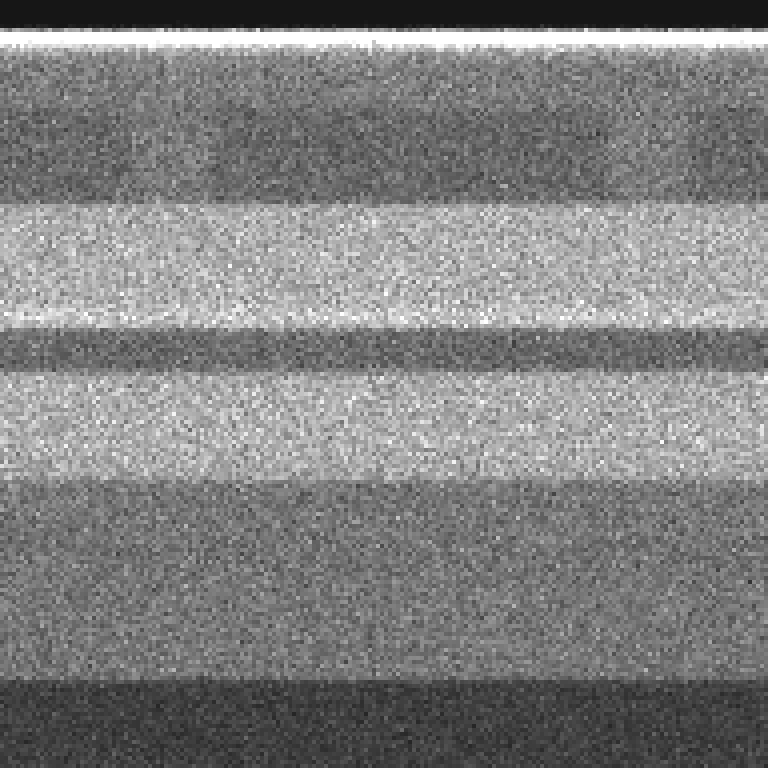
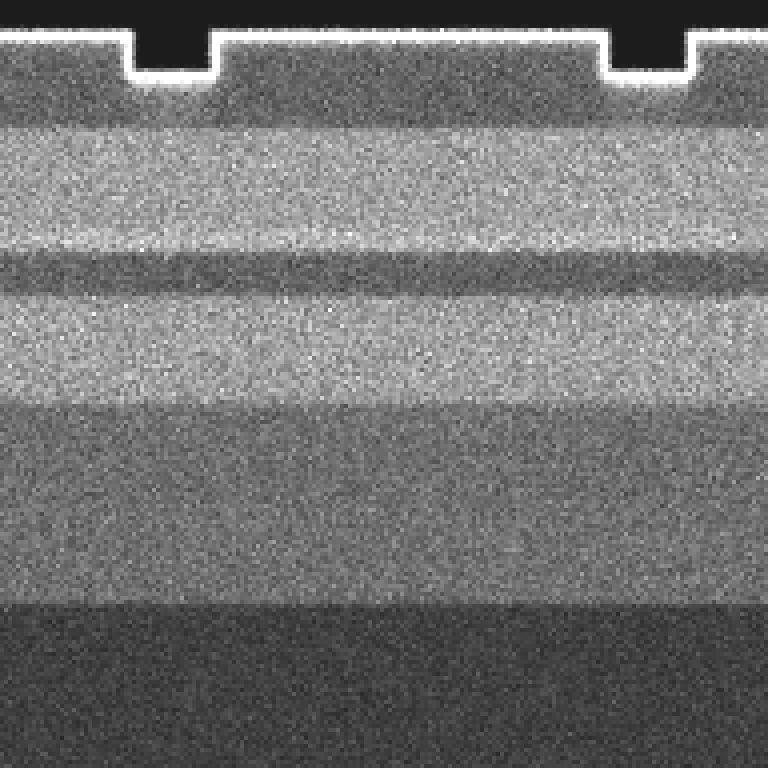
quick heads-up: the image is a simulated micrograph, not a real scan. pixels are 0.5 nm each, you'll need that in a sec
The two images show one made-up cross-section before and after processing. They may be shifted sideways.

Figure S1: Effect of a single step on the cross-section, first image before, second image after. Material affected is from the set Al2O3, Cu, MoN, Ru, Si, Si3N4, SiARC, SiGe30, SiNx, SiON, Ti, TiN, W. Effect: removed SiARC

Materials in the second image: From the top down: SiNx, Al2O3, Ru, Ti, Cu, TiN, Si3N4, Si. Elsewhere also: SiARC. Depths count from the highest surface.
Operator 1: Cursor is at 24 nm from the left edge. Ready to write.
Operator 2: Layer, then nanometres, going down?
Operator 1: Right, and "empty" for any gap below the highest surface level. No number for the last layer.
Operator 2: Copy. SiNx 48, Al2O3 52, Ru 10, Ti 22, Cu 54, TiN 48, Si3N4 52, Si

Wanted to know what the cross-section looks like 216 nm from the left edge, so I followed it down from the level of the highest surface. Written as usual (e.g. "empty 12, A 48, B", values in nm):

SiNx 48, Al2O3 52, Ru 10, Ti 22, Cu 54, TiN 48, Si3N4 52, Si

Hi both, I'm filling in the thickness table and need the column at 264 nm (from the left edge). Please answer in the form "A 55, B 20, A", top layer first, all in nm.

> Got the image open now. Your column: SiNx 48, Al2O3 52, Ru 10, Ti 22, Cu 54, TiN 48, Si3N4 52, Si